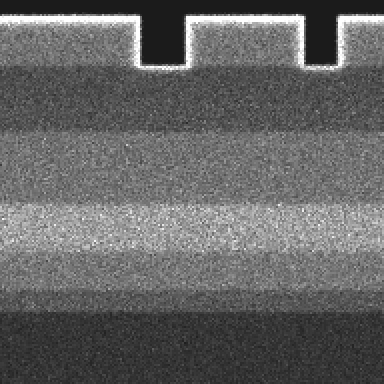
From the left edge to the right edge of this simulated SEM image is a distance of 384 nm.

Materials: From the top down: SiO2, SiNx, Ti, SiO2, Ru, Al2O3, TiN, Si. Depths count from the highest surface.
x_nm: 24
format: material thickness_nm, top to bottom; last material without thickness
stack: SiO2 50, SiNx 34, Ti 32, SiO2 72, Ru 48, Al2O3 38, TiN 22, Si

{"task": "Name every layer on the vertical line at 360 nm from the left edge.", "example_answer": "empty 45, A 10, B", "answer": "SiO2 50, SiNx 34, Ti 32, SiO2 72, Ru 48, Al2O3 38, TiN 22, Si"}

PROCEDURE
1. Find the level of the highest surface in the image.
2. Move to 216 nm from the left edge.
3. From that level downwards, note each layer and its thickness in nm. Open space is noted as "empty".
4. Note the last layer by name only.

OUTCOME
SiO2 50, SiNx 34, Ti 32, SiO2 72, Ru 48, Al2O3 38, TiN 22, Si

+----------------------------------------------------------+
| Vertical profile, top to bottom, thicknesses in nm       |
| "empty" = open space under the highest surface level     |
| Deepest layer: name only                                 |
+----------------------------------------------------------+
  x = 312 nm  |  empty 50, SiNx 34, Ti 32, SiO2 72, Ru 48, Al2O3 38, TiN 22, Si